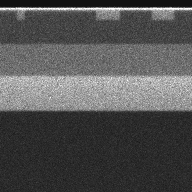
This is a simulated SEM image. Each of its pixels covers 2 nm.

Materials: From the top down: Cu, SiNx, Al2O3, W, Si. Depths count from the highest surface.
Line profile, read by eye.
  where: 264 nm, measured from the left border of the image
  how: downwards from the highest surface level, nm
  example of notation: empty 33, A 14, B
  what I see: SiNx 72, Al2O3 64, W 70, Si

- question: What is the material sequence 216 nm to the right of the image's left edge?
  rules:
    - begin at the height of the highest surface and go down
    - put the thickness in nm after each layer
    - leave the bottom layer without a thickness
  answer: Cu 24, SiNx 48, Al2O3 64, W 70, Si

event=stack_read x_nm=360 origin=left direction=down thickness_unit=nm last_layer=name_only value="SiNx 72, Al2O3 64, W 70, Si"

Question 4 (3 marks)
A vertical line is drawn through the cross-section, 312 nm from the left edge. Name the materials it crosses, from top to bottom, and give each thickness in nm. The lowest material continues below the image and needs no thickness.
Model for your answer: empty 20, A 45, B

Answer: Cu 24, SiNx 48, Al2O3 64, W 70, Si